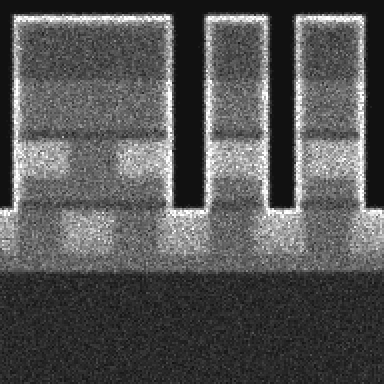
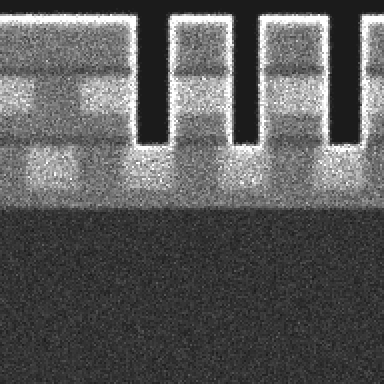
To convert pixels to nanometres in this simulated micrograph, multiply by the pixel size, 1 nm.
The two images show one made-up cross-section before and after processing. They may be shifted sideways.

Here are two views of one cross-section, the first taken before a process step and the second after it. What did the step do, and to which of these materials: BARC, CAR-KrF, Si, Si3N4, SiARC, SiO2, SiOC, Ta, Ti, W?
It removed SiARC.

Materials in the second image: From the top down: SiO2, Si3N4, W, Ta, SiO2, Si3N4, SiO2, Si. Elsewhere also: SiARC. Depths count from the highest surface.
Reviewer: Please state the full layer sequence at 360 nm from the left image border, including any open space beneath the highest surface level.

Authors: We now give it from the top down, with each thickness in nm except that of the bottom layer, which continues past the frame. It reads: empty 130, Ta 44, SiO2 18, Si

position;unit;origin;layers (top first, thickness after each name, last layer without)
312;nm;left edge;SiO2 50, Si3N4 10, W 30, Ta 8, SiO2 22, Si3N4 10, SiO2 62, Si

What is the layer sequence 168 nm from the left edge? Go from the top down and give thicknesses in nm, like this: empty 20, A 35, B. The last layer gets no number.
empty 130, Ta 44, SiO2 18, Si